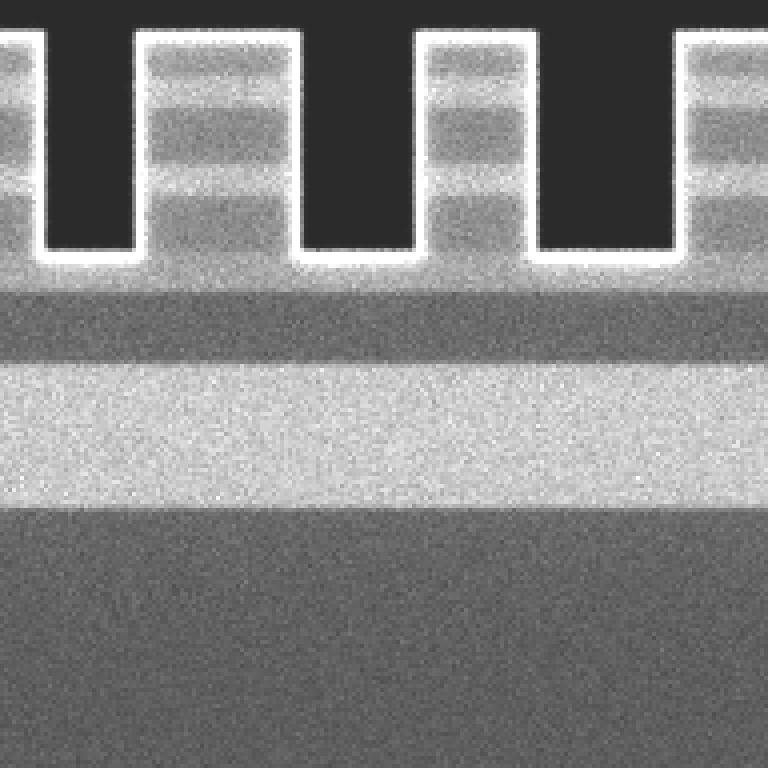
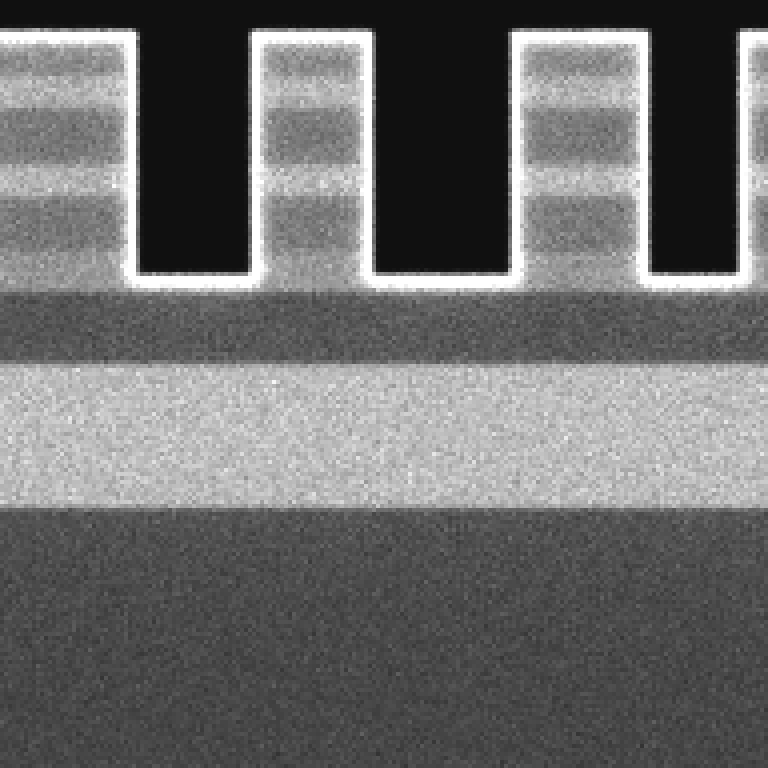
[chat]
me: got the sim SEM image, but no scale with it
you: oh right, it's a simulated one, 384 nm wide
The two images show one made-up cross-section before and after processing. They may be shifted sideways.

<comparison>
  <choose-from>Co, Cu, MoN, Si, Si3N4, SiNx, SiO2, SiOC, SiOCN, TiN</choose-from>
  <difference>Si3N4 removed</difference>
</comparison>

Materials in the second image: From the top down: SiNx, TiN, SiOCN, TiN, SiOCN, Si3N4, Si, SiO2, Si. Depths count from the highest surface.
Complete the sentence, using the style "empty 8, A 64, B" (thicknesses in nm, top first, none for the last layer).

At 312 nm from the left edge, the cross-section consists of SiNx 22, TiN 16, SiOCN 28, TiN 16, SiOCN 28, Si3N4 20, Si 36, SiO2 72, Si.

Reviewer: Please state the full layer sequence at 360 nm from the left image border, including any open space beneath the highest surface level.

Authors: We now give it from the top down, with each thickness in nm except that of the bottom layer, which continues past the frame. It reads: empty 122, Si3N4 8, Si 36, SiO2 72, Si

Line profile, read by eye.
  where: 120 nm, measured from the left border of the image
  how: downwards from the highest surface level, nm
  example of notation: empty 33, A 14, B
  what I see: empty 122, Si3N4 8, Si 36, SiO2 72, Si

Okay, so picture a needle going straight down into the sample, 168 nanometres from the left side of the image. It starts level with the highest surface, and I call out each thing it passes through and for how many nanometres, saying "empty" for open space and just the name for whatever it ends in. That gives SiNx 22, TiN 16, SiOCN 28, TiN 16, SiOCN 28, Si3N4 20, Si 36, SiO2 72, Si